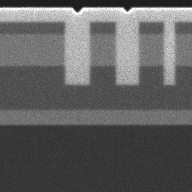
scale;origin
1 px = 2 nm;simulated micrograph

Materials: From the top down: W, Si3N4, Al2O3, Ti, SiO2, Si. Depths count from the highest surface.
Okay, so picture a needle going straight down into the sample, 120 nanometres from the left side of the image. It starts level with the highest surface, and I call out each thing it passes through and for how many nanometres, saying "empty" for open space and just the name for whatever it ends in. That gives W 28, Si3N4 24, Al2O3 64, Ti 88, SiO2 30, Si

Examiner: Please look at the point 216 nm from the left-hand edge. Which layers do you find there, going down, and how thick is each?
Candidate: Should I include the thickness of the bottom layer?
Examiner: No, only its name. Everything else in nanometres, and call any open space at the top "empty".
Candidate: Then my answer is W 28, Si3N4 24, Al2O3 64, Ti 88, SiO2 30, Si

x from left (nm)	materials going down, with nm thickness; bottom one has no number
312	W 28, Si3N4 24, Al2O3 64, Ti 88, SiO2 30, Si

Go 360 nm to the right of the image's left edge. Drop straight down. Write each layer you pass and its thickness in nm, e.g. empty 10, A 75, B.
W 28, Si3N4 24, Al2O3 64, Ti 88, SiO2 30, Si